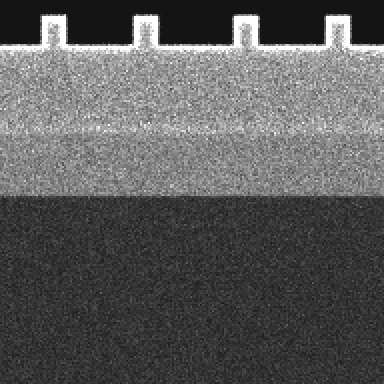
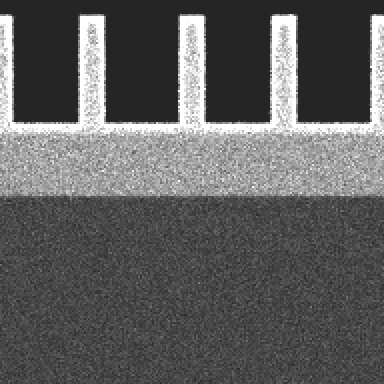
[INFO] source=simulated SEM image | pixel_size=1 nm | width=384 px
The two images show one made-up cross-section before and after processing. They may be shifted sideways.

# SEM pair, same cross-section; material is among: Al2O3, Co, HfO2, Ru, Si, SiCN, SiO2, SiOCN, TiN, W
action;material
removed;Co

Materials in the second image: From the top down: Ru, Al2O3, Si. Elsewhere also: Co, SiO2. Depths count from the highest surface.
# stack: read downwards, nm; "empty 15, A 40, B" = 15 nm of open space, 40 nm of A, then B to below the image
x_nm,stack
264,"empty 108, Ru 10, Al2O3 62, Si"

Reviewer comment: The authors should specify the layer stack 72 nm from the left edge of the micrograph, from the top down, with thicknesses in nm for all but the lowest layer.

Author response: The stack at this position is empty 108, Ru 10, Al2O3 62, Si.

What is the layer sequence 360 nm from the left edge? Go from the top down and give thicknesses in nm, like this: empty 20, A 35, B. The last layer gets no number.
empty 108, Ru 10, Al2O3 62, Si